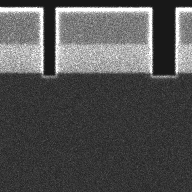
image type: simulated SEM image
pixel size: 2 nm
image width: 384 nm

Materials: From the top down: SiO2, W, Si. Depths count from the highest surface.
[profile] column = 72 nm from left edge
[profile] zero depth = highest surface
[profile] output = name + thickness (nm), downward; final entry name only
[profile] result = SiO2 72, W 58, Si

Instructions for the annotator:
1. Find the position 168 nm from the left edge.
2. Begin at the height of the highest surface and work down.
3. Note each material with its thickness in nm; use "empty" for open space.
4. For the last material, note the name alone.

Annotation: SiO2 72, W 58, Si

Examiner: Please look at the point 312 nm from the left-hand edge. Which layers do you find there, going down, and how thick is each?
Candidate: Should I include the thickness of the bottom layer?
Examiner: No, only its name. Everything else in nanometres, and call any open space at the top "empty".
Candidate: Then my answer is empty 136, Si